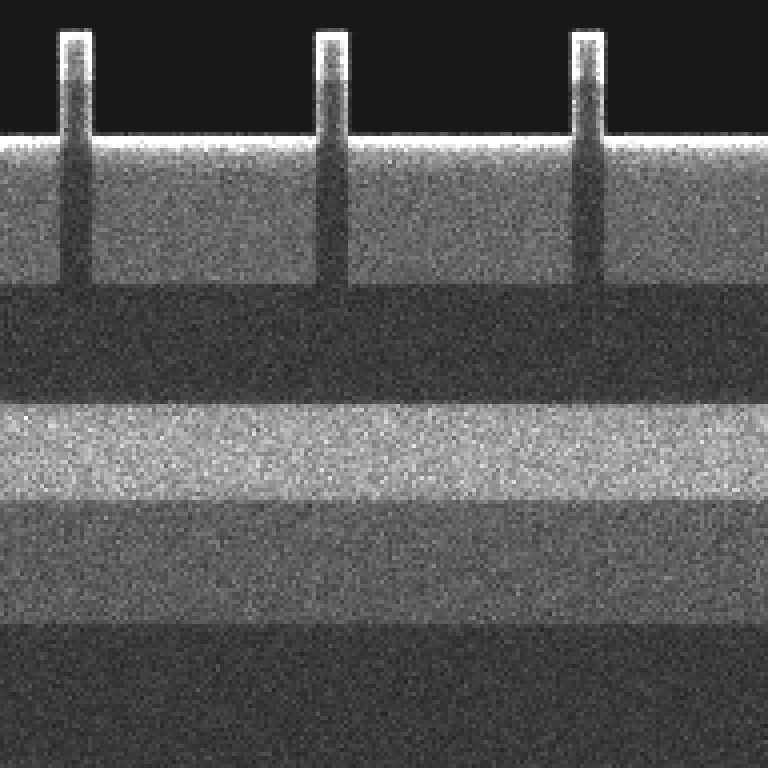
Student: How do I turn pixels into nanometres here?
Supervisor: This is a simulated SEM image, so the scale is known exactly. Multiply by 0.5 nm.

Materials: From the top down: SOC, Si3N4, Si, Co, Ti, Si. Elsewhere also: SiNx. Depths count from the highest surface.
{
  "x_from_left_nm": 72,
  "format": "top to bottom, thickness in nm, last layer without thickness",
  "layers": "empty 52, SOC 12, Si3N4 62, Si 60, Co 48, Ti 62, Si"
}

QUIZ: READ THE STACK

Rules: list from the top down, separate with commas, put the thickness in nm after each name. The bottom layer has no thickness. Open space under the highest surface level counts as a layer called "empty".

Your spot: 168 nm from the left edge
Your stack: SiNx 24, Si 162, Co 48, Ti 62, Si